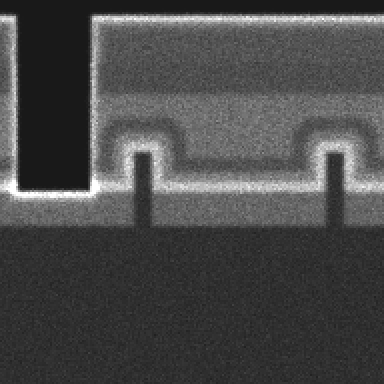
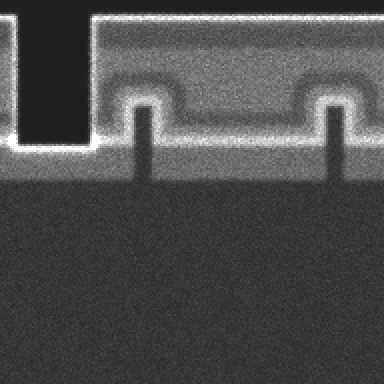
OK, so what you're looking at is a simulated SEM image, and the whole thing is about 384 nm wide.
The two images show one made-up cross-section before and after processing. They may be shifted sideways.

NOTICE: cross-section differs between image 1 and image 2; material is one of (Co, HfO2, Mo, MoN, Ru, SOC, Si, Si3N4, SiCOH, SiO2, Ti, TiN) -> removed: SOC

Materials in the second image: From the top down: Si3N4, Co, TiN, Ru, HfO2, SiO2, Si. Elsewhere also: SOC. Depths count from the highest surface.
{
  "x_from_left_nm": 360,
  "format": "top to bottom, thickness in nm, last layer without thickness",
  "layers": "Si3N4 32, Co 24, TiN 20, Ru 44, HfO2 10, SiO2 34, Si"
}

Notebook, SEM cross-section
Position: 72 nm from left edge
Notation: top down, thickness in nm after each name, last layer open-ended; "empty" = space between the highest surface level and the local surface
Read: empty 130, SiO2 34, Si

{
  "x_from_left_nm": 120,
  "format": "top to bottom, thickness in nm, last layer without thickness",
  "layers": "Si3N4 32, Co 24, TiN 16, Ru 48, HfO2 10, SiO2 34, Si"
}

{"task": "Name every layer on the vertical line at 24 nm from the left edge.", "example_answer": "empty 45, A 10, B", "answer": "empty 130, SiO2 34, Si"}